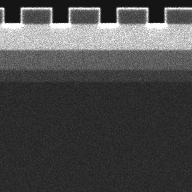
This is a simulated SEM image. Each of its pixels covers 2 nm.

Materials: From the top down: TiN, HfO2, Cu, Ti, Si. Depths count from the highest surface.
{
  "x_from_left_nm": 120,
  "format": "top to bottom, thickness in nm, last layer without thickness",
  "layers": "empty 32, HfO2 52, Cu 40, Ti 24, Si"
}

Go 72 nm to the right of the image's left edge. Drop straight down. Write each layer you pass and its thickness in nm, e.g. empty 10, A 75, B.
TiN 32, HfO2 52, Cu 40, Ti 24, Si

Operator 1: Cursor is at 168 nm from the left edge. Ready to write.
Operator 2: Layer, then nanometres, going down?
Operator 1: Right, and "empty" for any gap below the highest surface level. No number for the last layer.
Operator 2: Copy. TiN 32, HfO2 52, Cu 40, Ti 24, Si